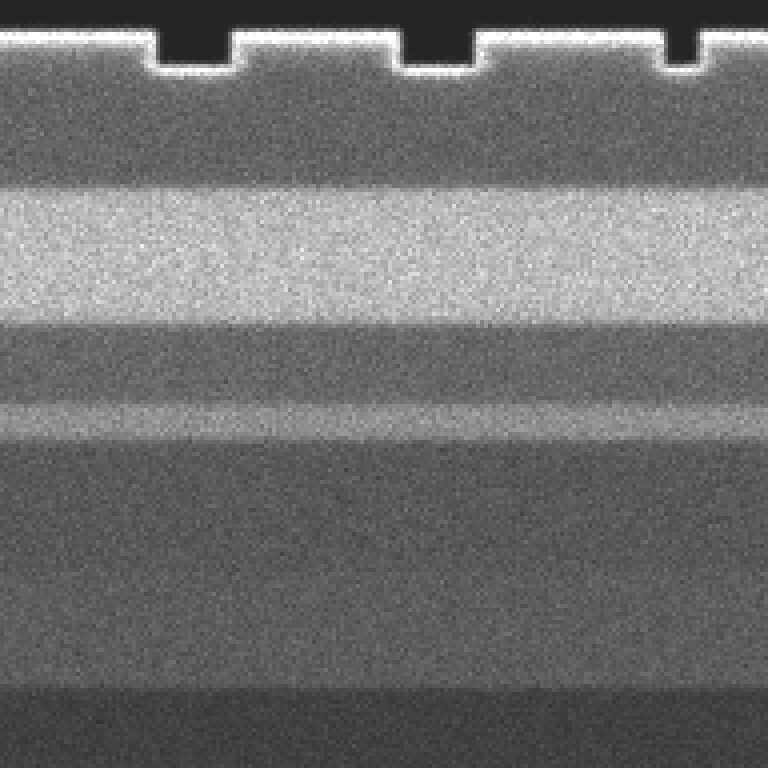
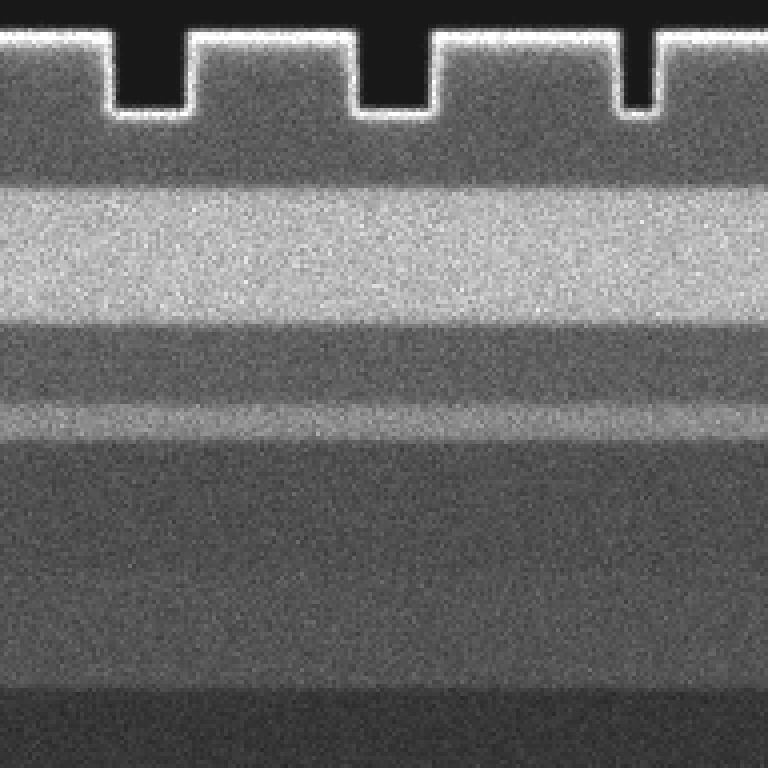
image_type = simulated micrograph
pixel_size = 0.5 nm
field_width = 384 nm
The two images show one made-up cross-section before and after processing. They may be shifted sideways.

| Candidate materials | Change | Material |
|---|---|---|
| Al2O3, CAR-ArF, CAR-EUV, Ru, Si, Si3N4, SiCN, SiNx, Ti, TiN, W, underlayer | removed | TiN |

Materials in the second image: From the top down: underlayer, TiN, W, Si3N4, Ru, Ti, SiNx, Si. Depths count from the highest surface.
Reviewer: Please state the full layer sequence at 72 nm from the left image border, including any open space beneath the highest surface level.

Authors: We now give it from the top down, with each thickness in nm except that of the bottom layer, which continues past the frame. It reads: empty 40, TiN 38, W 68, Si3N4 40, Ru 18, Ti 66, SiNx 58, Si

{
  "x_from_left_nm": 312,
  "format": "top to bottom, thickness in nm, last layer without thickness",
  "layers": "empty 40, TiN 38, W 68, Si3N4 40, Ru 18, Ti 66, SiNx 58, Si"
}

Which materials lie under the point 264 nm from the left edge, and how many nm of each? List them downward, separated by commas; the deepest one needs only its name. underlayer 18, TiN 60, W 68, Si3N4 40, Ru 18, Ti 66, SiNx 58, Si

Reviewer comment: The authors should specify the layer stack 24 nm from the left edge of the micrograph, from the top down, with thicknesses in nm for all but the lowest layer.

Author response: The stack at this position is underlayer 18, TiN 60, W 68, Si3N4 40, Ru 18, Ti 66, SiNx 58, Si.